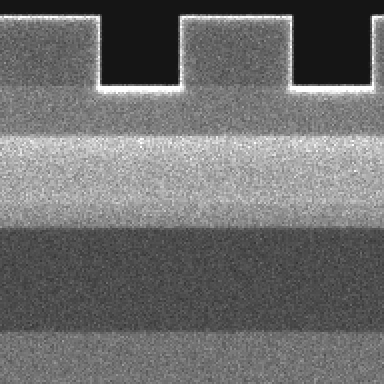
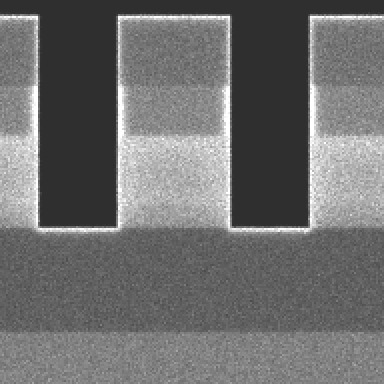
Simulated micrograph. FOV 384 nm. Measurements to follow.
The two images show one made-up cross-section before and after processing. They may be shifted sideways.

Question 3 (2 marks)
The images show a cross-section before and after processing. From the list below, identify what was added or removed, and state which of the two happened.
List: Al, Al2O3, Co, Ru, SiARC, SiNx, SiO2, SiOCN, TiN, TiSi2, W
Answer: Al2O3 and Co and Ru and W was removed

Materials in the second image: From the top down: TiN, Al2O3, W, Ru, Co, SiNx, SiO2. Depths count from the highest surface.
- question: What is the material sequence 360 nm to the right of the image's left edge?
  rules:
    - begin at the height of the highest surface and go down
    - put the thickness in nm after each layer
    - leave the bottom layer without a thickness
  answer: TiN 70, Al2O3 50, W 68, Ru 12, Co 12, SiNx 104, SiO2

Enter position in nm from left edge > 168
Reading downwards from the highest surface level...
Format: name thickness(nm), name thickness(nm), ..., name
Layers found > TiN 70, Al2O3 50, W 68, Ru 12, Co 12, SiNx 104, SiO2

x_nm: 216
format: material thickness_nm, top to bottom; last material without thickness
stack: TiN 70, Al2O3 50, W 68, Ru 12, Co 12, SiNx 104, SiO2